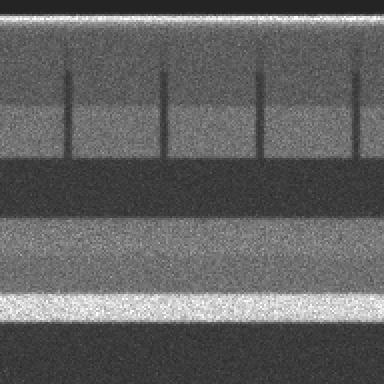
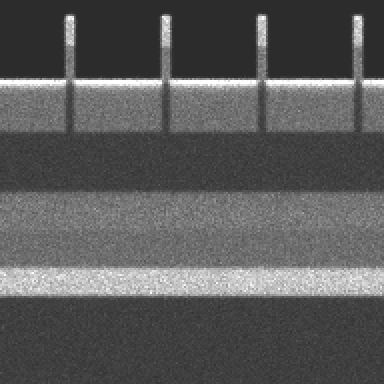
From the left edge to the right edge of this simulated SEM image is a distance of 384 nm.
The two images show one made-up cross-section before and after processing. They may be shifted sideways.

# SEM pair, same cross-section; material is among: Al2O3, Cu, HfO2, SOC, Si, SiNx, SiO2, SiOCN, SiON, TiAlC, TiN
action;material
removed;SOC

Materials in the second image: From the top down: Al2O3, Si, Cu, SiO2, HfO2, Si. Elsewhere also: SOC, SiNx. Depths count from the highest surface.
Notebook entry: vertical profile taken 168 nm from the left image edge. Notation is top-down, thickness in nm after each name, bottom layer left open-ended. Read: SiNx 30, Si 146, Cu 38, SiO2 38, HfO2 28, Si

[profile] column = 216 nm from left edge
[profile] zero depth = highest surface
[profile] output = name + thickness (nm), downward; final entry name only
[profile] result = empty 64, Al2O3 52, Si 60, Cu 38, SiO2 38, HfO2 28, Si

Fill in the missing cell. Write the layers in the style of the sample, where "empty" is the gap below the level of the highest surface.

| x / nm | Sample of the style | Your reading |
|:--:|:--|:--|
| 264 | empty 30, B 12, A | SiNx 30, Si 146, Cu 38, SiO2 38, HfO2 28, Si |